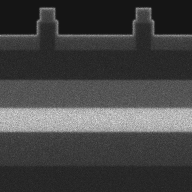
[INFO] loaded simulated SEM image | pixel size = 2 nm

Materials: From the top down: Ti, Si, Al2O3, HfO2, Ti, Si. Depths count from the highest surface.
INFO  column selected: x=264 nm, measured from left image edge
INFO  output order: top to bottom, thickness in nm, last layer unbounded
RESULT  empty 54, Ti 30, Si 60, Al2O3 56, HfO2 48, Ti 68, Si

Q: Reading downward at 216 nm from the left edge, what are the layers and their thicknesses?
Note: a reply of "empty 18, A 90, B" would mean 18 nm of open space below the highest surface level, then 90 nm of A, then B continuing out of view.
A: empty 54, Ti 30, Si 60, Al2O3 56, HfO2 48, Ti 68, Si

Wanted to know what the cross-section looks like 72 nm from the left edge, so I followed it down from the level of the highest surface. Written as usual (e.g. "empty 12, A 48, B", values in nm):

empty 54, Ti 30, Si 60, Al2O3 56, HfO2 48, Ti 68, Si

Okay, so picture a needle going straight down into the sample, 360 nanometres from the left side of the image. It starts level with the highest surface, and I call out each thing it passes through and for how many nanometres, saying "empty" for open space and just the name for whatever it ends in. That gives empty 54, Ti 30, Si 60, Al2O3 56, HfO2 48, Ti 68, Si